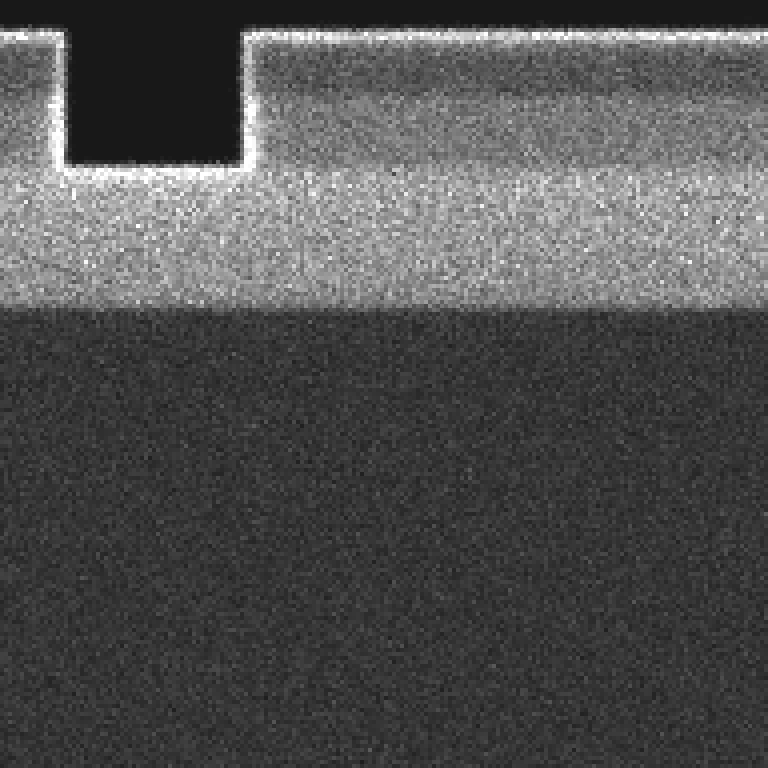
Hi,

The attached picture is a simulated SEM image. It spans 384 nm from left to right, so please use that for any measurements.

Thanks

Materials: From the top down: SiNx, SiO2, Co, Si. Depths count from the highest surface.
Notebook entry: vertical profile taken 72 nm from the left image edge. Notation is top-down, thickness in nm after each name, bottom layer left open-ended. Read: empty 68, Co 70, Si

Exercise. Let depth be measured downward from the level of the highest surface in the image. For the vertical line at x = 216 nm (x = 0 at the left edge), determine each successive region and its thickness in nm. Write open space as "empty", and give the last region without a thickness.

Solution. SiNx 32, SiO2 36, Co 70, Si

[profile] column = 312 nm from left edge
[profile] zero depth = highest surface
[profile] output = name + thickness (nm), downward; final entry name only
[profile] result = SiNx 32, SiO2 36, Co 70, Si